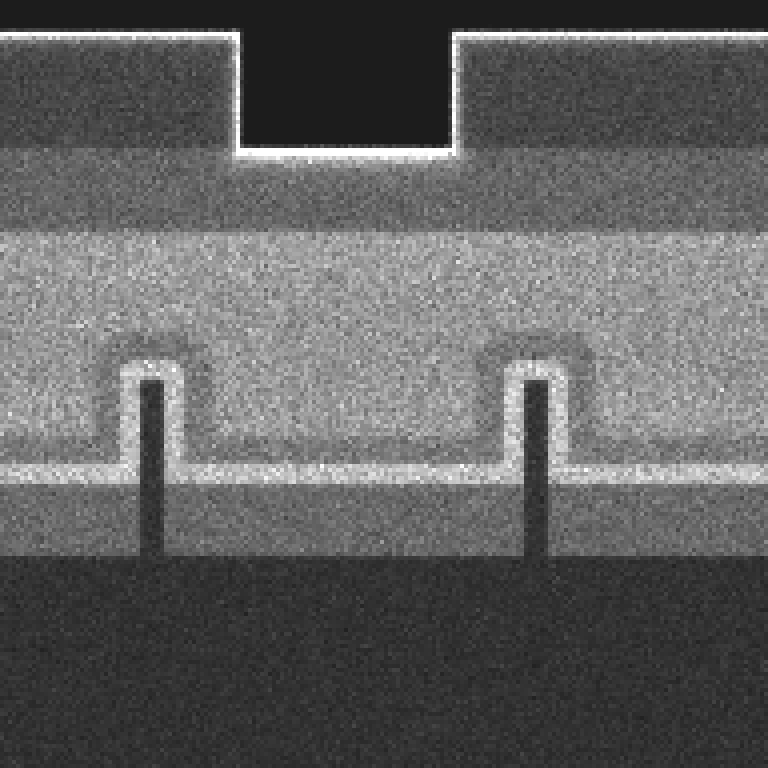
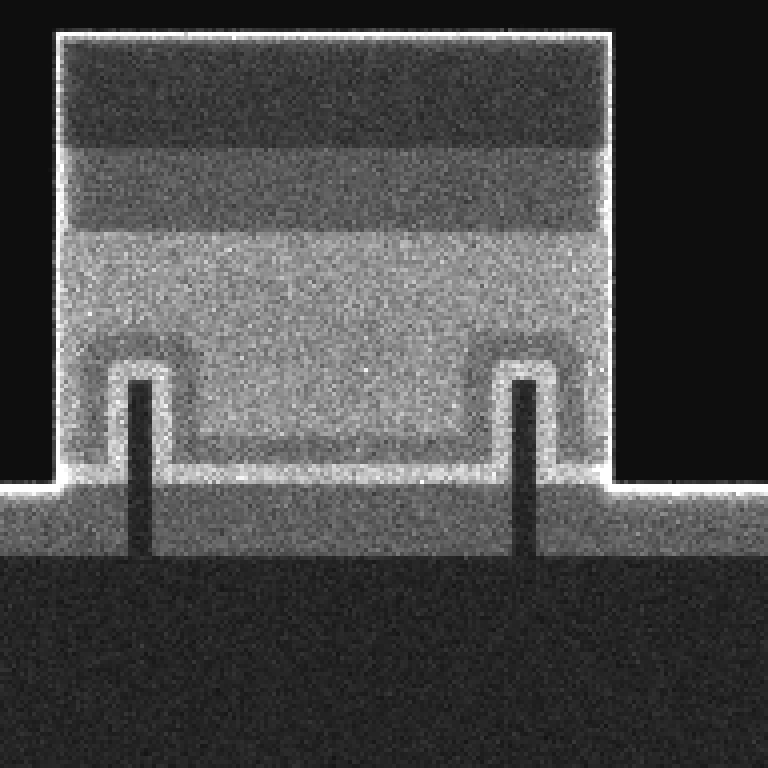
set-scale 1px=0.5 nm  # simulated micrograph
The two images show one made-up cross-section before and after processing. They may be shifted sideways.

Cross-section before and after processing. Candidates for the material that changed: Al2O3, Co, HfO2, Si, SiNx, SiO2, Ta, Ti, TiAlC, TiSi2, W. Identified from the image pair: Co and HfO2 and SiO2 and W (removed).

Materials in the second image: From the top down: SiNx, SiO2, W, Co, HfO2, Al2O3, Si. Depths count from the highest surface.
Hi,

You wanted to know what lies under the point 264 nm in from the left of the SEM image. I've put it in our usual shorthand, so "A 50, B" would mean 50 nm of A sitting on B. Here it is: SiNx 58, SiO2 42, W 50, Co 14, HfO2 10, Si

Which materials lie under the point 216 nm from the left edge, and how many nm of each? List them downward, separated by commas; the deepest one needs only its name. SiNx 58, SiO2 42, W 102, Co 14, HfO2 10, Al2O3 36, Si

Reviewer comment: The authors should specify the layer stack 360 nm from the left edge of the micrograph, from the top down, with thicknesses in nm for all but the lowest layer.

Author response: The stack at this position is empty 226, Al2O3 36, Si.